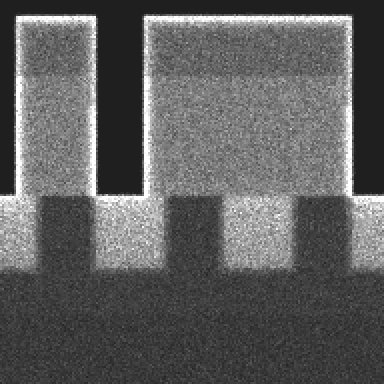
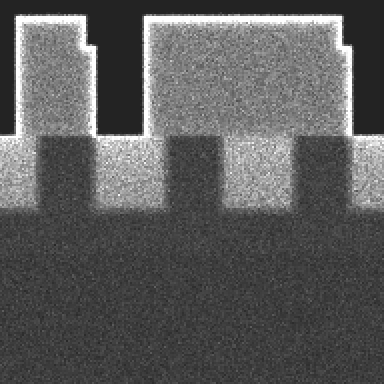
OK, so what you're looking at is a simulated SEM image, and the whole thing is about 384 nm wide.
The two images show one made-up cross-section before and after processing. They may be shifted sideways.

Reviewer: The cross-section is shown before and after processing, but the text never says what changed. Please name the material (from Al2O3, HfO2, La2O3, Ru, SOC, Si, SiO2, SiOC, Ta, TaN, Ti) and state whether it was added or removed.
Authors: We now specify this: SOC, removed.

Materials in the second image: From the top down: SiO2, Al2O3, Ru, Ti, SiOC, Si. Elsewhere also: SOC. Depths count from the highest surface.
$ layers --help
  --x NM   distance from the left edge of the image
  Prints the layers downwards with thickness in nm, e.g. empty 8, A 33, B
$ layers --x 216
SiO2 106, Al2O3 14, SiOC 118, Si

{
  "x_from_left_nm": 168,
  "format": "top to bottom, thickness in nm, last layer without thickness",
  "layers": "SiO2 106, Al2O3 14, Ti 78, SiOC 40, Si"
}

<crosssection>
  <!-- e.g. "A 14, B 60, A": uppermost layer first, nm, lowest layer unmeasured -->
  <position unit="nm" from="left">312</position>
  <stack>SiO2 106, Al2O3 14, SiOC 118, Si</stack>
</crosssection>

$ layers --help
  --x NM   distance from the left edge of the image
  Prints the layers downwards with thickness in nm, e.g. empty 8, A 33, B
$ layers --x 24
SiO2 106, Al2O3 14, Ru 72, Ti 6, SiOC 40, Si